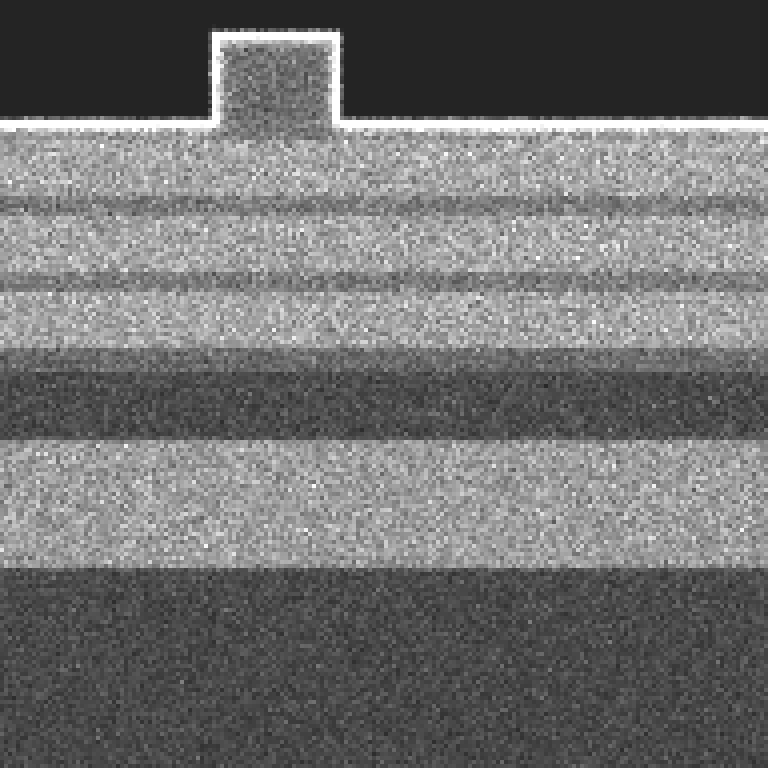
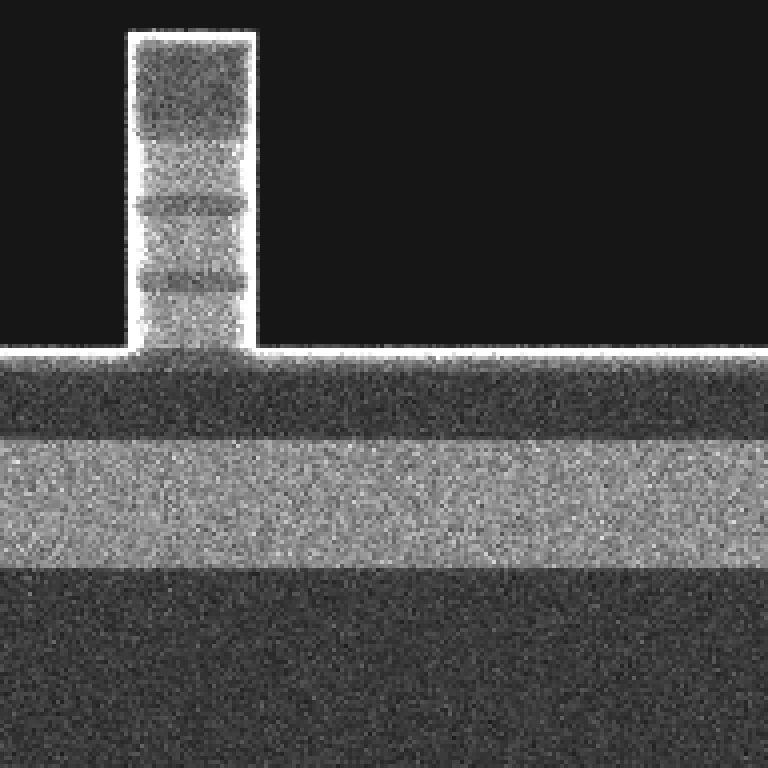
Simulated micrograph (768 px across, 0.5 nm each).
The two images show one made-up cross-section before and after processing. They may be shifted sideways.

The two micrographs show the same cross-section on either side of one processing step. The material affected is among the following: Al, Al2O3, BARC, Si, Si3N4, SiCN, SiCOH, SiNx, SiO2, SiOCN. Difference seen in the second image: Al2O3 and Si3N4 removed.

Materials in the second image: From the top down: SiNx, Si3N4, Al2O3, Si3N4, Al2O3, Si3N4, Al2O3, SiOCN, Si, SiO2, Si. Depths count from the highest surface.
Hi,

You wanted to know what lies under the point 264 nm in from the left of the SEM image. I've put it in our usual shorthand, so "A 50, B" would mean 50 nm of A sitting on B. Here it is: empty 158, SiOCN 12, Si 34, SiO2 64, Si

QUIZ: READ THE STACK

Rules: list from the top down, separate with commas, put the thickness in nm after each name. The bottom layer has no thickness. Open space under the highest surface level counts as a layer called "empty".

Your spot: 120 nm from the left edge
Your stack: SiNx 44, Si3N4 10, Al2O3 28, Si3N4 10, Al2O3 28, Si3N4 10, Al2O3 28, SiOCN 12, Si 34, SiO2 64, Si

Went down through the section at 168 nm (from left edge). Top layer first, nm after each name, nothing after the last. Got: empty 158, SiOCN 12, Si 34, SiO2 64, Si